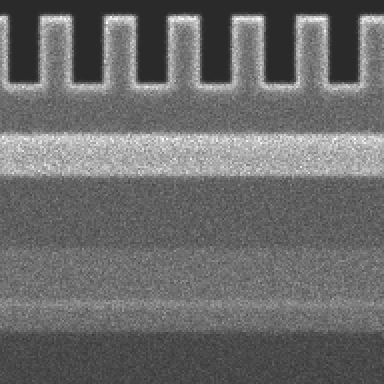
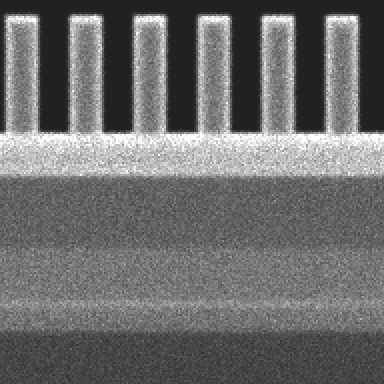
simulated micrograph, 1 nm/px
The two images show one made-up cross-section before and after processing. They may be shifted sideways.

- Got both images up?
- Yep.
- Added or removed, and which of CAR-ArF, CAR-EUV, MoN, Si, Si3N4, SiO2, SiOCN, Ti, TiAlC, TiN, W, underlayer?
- removed, underlayer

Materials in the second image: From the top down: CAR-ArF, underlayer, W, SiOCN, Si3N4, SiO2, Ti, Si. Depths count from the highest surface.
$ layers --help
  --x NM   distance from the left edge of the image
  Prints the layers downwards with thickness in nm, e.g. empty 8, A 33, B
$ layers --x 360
empty 118, W 42, SiOCN 72, Si3N4 52, SiO2 8, Ti 24, Si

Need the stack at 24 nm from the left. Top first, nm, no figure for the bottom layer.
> CAR-ArF 68, underlayer 50, W 42, SiOCN 72, Si3N4 52, SiO2 8, Ti 24, Si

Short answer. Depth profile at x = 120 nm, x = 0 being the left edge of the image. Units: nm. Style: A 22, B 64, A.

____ empty 118, W 42, SiOCN 72, Si3N4 52, SiO2 8, Ti 24, Si